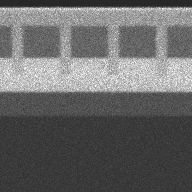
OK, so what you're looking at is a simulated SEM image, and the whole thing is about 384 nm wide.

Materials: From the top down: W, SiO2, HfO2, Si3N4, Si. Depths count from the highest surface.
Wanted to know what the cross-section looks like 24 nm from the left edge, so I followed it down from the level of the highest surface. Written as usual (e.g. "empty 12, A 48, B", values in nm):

W 134, HfO2 34, Si3N4 48, Si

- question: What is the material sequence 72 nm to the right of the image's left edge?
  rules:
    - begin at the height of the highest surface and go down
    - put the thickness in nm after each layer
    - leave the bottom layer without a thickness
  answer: W 36, SiO2 64, HfO2 68, Si3N4 48, Si